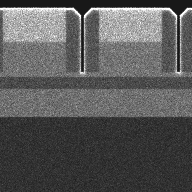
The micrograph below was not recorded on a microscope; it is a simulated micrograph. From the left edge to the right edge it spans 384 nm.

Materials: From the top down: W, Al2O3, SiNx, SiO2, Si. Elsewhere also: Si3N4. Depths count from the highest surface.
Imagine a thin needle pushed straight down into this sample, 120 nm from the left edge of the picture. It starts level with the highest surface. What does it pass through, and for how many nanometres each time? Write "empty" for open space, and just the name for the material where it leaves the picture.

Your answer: W 68, Al2O3 70, SiNx 24, SiO2 56, Si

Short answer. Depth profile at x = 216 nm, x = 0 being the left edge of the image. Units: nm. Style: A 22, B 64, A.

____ W 68, Al2O3 70, SiNx 24, SiO2 56, Si